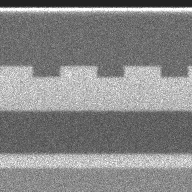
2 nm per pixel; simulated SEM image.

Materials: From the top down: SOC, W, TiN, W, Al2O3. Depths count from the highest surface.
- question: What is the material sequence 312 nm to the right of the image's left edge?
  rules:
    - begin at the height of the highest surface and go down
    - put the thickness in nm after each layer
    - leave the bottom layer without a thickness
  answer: SOC 116, W 90, TiN 86, W 28, Al2O3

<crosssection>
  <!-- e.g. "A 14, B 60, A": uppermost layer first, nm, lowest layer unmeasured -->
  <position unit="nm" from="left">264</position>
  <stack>SOC 116, W 90, TiN 86, W 28, Al2O3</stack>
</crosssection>